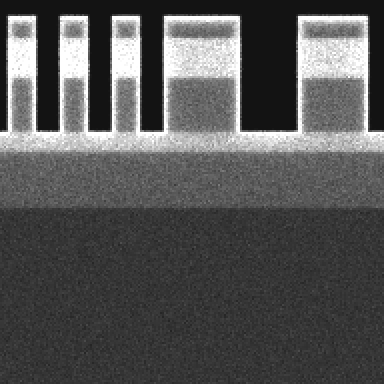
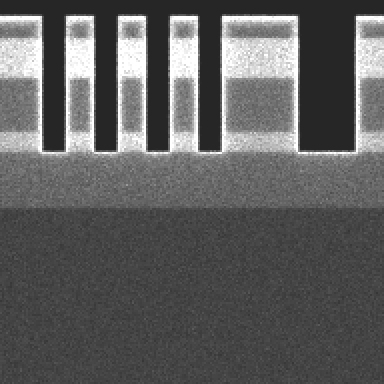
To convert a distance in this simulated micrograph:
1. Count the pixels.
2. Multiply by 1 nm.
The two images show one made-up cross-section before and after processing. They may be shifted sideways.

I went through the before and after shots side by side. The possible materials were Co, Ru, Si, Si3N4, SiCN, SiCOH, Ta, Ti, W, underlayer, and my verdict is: removed, Ru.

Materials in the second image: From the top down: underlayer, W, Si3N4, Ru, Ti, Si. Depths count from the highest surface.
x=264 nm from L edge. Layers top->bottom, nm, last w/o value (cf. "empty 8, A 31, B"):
underlayer 22, W 40, Si3N4 54, Ru 20, Ti 56, Si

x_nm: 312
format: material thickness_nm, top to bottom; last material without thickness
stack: empty 136, Ti 56, Si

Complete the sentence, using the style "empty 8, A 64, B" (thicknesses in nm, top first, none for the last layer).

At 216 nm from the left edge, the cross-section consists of empty 136, Ti 56, Si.